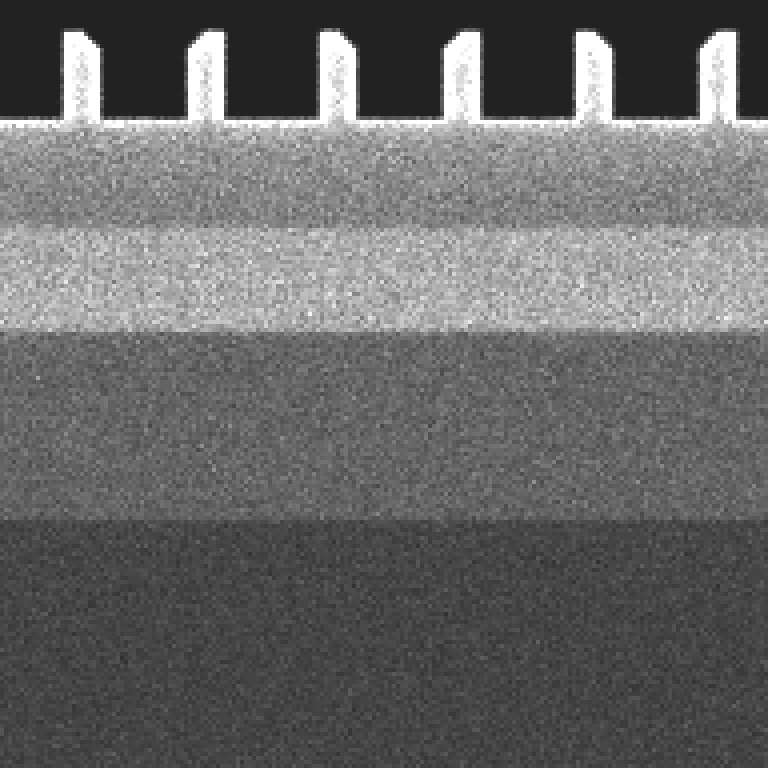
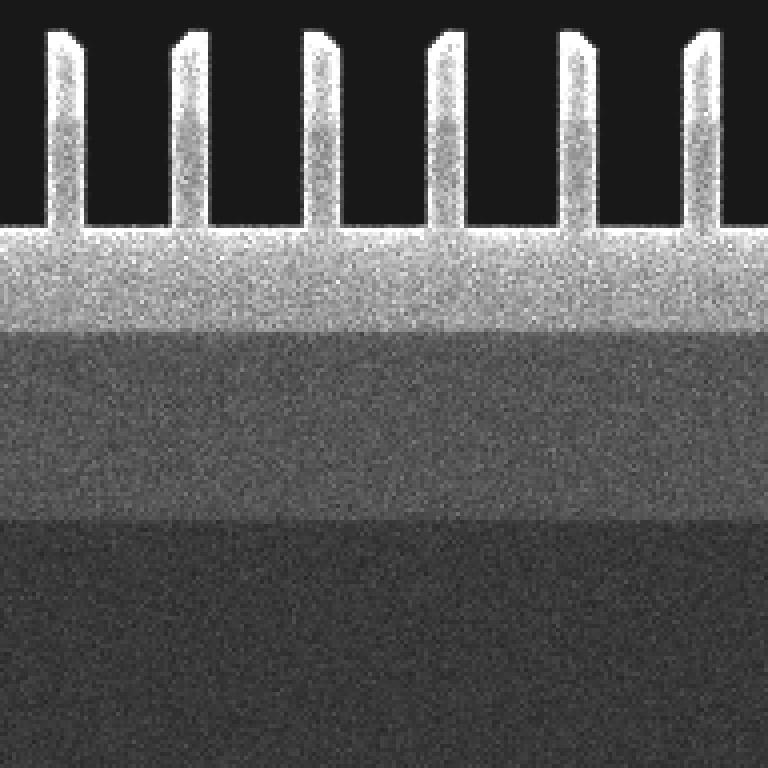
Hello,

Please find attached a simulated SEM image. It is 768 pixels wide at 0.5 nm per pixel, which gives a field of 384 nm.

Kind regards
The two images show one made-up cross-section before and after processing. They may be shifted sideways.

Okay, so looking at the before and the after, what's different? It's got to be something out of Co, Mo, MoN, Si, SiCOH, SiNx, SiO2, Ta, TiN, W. TiN, removed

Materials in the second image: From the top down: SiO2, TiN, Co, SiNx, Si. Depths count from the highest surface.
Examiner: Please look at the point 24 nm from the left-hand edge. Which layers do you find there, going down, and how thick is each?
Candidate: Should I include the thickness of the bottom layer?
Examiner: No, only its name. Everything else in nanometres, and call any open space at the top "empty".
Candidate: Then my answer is SiO2 44, TiN 54, Co 52, SiNx 94, Si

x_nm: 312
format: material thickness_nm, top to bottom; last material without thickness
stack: empty 98, Co 52, SiNx 94, Si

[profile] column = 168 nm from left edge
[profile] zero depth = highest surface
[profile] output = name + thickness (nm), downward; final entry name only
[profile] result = empty 8, SiO2 36, TiN 54, Co 52, SiNx 94, Si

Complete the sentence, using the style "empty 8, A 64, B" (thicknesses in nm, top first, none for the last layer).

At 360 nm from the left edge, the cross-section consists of empty 98, Co 52, SiNx 94, Si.